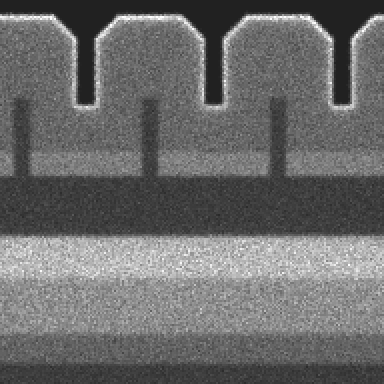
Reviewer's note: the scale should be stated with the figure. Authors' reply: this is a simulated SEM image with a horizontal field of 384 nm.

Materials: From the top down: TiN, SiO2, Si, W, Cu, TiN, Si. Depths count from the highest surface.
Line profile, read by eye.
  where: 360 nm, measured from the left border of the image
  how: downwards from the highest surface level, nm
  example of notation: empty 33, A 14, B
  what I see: empty 14, TiN 122, SiO2 24, Si 60, W 42, Cu 56, TiN 30, Si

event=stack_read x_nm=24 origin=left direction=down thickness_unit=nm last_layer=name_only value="TiN 82, Si 138, W 42, Cu 56, TiN 30, Si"